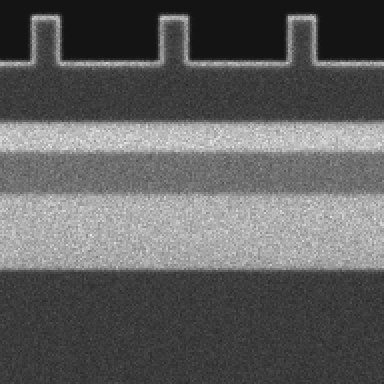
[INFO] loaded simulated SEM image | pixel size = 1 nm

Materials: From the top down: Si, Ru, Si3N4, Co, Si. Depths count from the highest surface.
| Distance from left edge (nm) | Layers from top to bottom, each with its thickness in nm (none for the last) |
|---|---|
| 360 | empty 46, Si 60, Ru 30, Si3N4 42, Co 76, Si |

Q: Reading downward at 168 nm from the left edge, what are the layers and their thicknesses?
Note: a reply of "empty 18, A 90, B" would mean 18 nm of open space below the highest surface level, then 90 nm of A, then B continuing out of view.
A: Si 106, Ru 30, Si3N4 42, Co 76, Si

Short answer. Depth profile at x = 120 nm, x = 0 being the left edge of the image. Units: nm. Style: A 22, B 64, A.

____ empty 46, Si 60, Ru 30, Si3N4 42, Co 76, Si